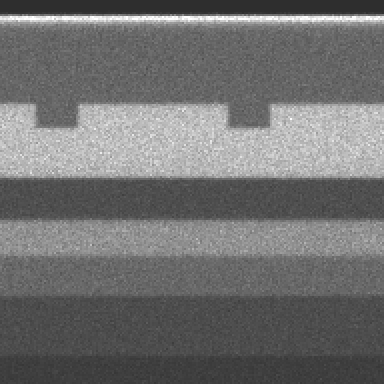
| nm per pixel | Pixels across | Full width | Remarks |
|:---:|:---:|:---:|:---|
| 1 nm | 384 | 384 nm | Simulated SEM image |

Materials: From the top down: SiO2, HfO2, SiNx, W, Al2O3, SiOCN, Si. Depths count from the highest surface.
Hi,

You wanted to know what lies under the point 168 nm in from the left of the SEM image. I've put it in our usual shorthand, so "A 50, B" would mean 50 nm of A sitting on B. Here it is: SiO2 88, HfO2 74, SiNx 42, W 36, Al2O3 40, SiOCN 60, Si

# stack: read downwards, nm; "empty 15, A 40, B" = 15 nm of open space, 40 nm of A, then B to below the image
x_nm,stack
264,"SiO2 112, HfO2 50, SiNx 42, W 36, Al2O3 40, SiOCN 60, Si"